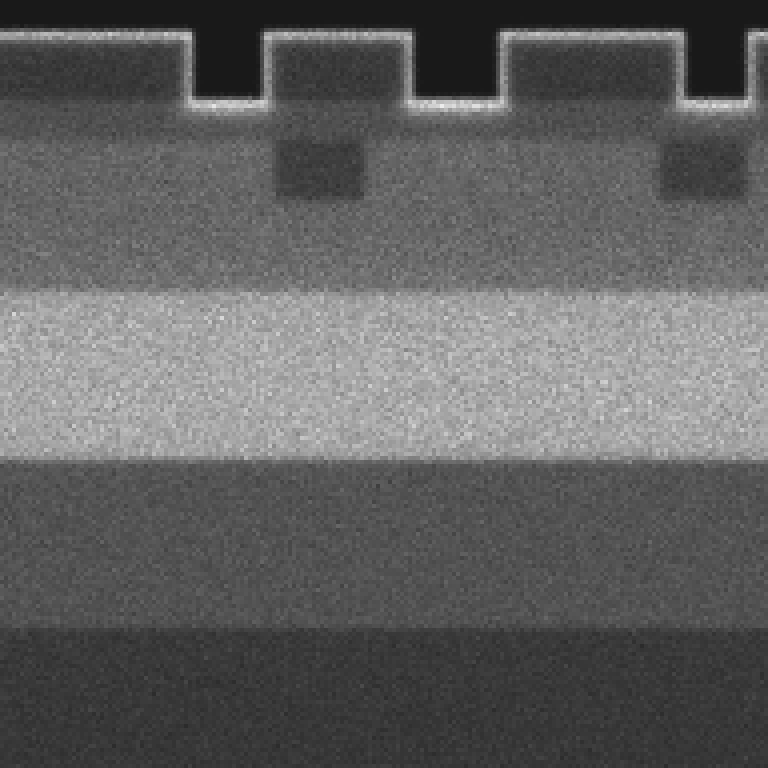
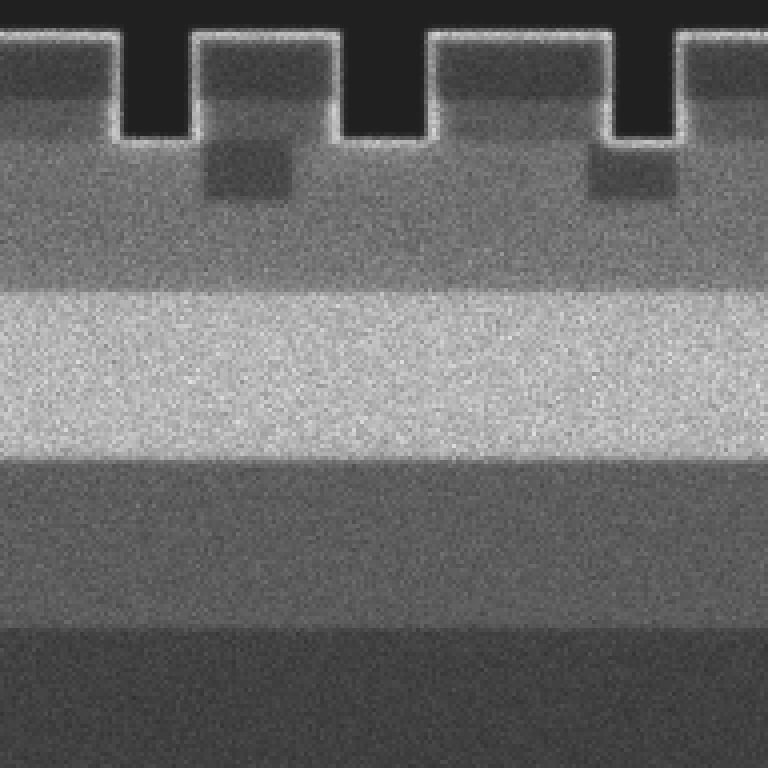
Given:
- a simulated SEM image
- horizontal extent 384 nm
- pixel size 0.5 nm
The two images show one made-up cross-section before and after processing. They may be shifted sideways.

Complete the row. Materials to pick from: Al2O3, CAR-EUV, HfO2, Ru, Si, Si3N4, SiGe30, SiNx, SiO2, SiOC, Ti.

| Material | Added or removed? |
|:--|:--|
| SiO2 | removed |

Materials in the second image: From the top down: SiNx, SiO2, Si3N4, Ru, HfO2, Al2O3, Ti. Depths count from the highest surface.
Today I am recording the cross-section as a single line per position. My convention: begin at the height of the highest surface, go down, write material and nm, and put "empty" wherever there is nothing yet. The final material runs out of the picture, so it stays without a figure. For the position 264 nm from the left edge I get SiNx 34, SiO2 20, Ru 76, HfO2 84, Al2O3 84, Ti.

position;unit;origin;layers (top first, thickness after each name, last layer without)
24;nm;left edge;SiNx 34, SiO2 20, Ru 76, HfO2 84, Al2O3 84, Ti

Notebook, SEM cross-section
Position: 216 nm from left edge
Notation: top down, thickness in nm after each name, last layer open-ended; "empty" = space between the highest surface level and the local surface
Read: SiNx 34, SiO2 20, Ru 76, HfO2 84, Al2O3 84, Ti